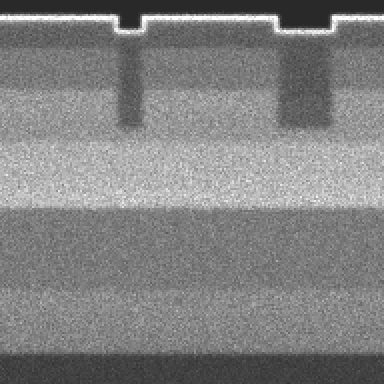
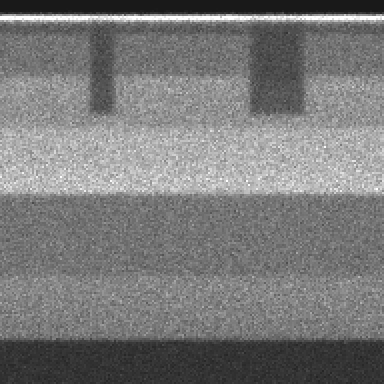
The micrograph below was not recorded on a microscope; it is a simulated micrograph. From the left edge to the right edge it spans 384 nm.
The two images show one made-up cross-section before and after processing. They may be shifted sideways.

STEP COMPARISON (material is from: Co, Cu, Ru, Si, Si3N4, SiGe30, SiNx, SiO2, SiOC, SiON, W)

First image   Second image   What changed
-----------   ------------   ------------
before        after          Si3N4, removed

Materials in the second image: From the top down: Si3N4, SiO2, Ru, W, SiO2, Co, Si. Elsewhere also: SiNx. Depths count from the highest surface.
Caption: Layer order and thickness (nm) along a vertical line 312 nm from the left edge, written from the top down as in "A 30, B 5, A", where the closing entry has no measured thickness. Si3N4 18, SiO2 42, Ru 52, W 66, SiO2 82, Co 64, Si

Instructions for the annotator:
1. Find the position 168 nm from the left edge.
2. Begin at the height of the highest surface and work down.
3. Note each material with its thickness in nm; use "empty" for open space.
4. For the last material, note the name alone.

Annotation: Si3N4 18, SiO2 42, Ru 52, W 66, SiO2 82, Co 64, Si